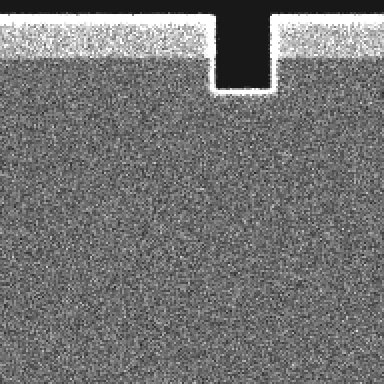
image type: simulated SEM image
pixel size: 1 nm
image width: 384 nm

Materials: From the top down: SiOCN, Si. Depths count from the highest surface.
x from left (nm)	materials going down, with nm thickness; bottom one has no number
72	SiOCN 42, Si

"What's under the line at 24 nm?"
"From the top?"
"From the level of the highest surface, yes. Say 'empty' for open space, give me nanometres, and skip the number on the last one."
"SiOCN 42, Si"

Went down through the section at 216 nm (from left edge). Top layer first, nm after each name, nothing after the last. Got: empty 74, Si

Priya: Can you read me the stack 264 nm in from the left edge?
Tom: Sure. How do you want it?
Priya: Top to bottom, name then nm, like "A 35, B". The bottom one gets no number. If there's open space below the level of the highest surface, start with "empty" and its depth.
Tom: empty 74, Si